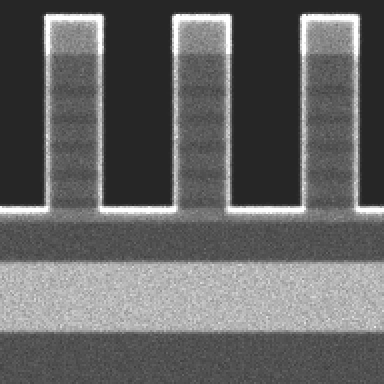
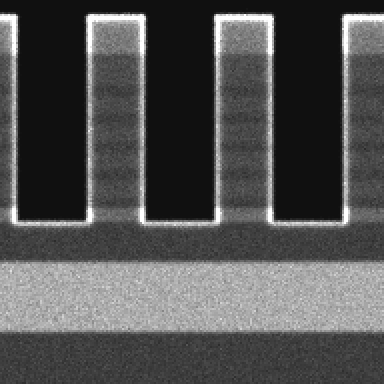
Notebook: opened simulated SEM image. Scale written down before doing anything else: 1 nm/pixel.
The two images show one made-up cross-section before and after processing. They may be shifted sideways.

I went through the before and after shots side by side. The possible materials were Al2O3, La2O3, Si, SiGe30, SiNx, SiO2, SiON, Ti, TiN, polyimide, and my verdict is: removed, SiNx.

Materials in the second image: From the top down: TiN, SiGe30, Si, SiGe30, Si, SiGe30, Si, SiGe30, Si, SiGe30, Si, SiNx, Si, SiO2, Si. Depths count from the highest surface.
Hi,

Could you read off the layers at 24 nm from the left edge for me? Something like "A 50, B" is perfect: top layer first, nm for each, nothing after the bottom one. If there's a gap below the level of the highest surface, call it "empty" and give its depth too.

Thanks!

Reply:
empty 206, Si 40, SiO2 70, Si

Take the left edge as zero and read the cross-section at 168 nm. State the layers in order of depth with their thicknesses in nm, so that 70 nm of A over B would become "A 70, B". empty 206, Si 40, SiO2 70, Si